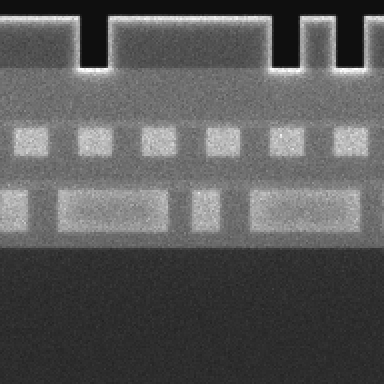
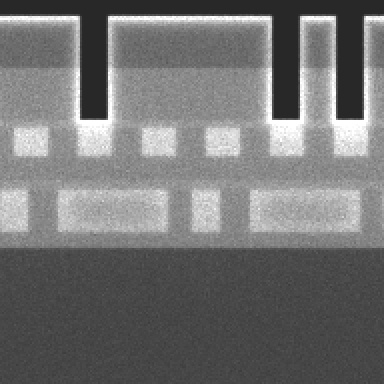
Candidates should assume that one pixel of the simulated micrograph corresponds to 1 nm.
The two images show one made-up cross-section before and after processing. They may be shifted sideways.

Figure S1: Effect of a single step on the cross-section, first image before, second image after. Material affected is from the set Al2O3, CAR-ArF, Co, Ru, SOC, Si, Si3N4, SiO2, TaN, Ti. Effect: removed SiO2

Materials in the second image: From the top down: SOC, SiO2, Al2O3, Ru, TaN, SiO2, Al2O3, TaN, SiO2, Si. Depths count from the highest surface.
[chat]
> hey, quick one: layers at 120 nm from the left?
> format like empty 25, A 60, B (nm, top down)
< SOC 52, SiO2 52, Al2O3 8, SiO2 52, Al2O3 10, Ru 32, TaN 10, SiO2 16, Si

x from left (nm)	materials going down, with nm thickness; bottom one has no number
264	SOC 52, SiO2 52, Al2O3 8, SiO2 52, Al2O3 10, Ru 32, TaN 10, SiO2 16, Si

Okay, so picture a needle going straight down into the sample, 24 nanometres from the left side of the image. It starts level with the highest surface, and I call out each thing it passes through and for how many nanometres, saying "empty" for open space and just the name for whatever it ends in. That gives SOC 52, SiO2 52, Al2O3 8, Ru 18, TaN 10, SiO2 24, Al2O3 10, TaN 42, SiO2 16, Si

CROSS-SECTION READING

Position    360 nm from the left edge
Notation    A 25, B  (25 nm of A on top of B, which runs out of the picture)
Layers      empty 104, Al2O3 8, TaN 28, SiO2 24, Al2O3 10, SiO2 58, Si